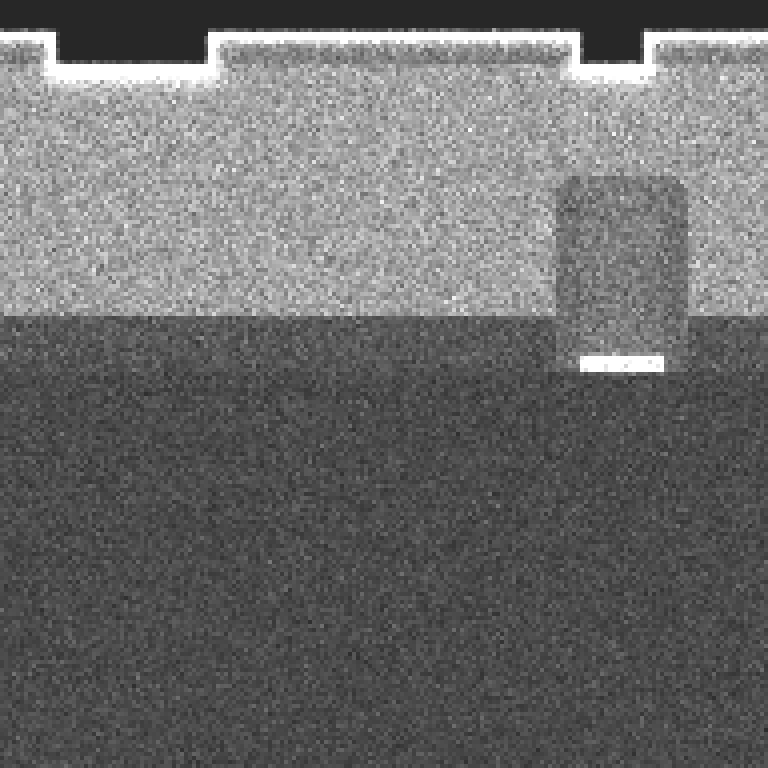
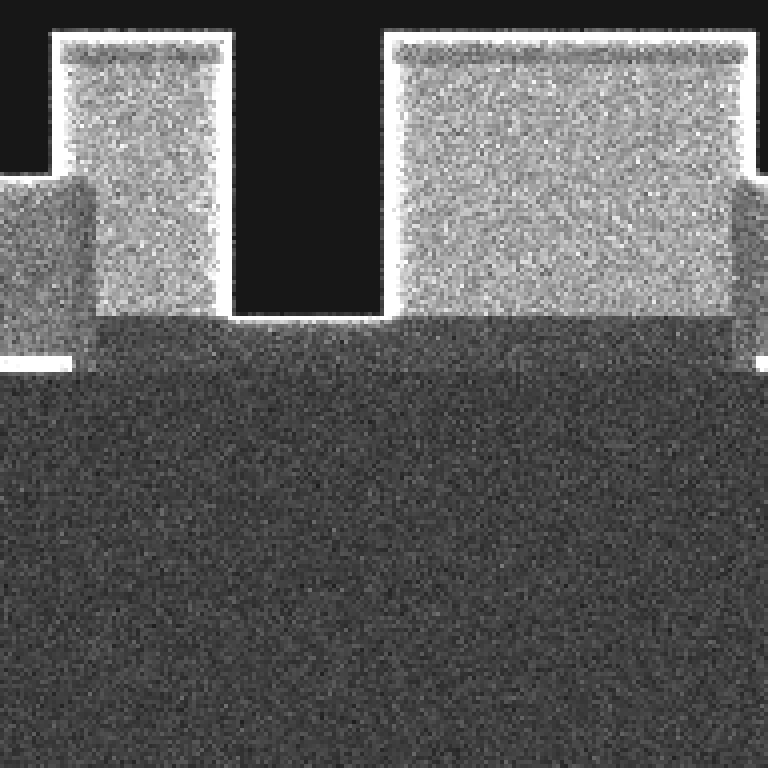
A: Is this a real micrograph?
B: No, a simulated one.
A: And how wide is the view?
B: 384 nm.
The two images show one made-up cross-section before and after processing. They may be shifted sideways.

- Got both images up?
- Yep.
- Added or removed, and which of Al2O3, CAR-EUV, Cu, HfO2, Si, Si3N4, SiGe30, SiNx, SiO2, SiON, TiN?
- removed, SiO2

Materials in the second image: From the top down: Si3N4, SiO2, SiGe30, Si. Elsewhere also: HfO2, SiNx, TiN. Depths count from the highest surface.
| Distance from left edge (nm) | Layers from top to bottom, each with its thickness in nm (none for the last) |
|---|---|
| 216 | Si3N4 16, SiO2 126, SiGe30 28, Si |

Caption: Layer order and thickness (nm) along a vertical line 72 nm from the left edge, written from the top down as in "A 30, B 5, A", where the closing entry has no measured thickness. Si3N4 16, SiO2 126, SiGe30 28, Si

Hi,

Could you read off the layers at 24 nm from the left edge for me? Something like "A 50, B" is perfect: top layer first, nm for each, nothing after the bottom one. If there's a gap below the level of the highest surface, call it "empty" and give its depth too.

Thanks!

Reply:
empty 72, TiN 90, HfO2 8, Si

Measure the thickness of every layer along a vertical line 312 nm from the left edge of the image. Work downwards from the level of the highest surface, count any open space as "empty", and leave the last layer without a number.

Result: Si3N4 16, SiO2 126, SiGe30 28, Si